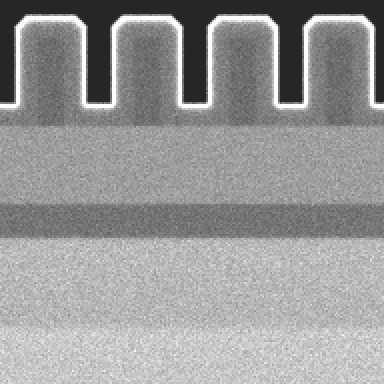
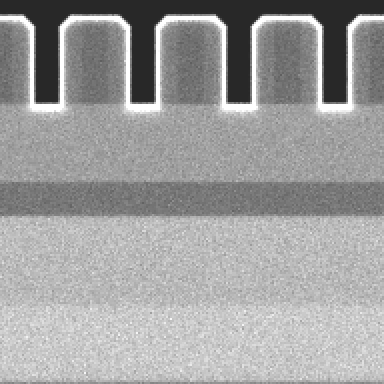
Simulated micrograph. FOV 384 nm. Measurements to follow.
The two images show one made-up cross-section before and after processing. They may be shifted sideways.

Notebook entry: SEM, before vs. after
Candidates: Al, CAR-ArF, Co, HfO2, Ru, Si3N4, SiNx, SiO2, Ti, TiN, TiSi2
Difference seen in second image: Si3N4 removed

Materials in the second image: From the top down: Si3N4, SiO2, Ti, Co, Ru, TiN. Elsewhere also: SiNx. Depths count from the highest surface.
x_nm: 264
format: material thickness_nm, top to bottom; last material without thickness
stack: Si3N4 88, SiO2 78, Ti 34, Co 90, Ru 76, TiN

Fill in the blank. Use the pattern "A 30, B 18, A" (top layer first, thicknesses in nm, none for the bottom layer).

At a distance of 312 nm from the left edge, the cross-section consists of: empty 2, Si3N4 86, SiO2 78, Ti 34, Co 90, Ru 76, TiN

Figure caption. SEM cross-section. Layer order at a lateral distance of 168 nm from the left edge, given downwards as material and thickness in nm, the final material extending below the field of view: Si3N4 88, SiO2 78, Ti 34, Co 90, Ru 76, TiN